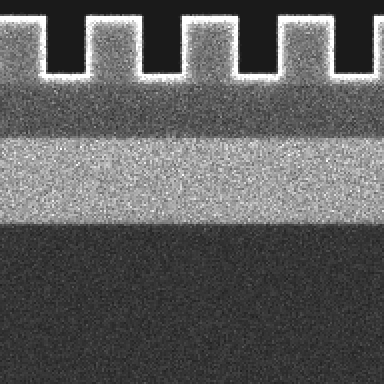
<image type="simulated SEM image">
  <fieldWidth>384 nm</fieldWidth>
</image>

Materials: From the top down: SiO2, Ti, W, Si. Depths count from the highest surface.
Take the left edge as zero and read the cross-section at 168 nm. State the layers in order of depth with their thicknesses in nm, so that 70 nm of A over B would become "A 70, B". empty 58, SiO2 10, Ti 54, W 86, Si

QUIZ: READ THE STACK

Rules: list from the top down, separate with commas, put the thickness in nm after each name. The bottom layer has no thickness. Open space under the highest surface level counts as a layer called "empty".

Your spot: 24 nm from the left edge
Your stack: SiO2 68, Ti 54, W 86, Si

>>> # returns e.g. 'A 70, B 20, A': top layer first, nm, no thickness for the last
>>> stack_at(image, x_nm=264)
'empty 58, SiO2 10, Ti 54, W 86, Si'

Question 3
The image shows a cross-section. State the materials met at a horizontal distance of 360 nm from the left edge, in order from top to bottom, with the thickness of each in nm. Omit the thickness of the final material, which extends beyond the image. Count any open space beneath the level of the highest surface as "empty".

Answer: empty 58, SiO2 10, Ti 54, W 86, Si